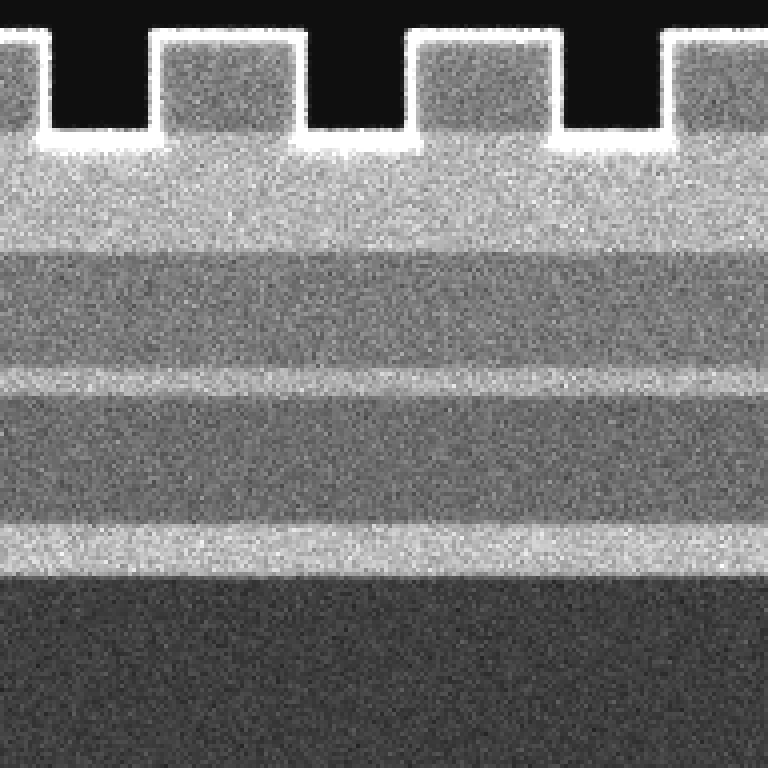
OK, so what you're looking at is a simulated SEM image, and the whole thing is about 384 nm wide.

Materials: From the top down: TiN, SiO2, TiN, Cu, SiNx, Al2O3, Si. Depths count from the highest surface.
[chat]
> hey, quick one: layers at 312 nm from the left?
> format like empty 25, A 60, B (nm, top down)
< empty 50, SiO2 60, TiN 58, Cu 14, SiNx 64, Al2O3 26, Si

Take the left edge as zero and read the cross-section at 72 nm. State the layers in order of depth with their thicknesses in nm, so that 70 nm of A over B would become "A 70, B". empty 50, SiO2 60, TiN 58, Cu 14, SiNx 64, Al2O3 26, Si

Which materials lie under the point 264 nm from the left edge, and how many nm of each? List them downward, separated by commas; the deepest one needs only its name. TiN 50, SiO2 60, TiN 58, Cu 14, SiNx 64, Al2O3 26, Si